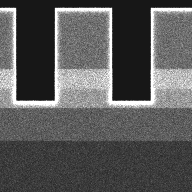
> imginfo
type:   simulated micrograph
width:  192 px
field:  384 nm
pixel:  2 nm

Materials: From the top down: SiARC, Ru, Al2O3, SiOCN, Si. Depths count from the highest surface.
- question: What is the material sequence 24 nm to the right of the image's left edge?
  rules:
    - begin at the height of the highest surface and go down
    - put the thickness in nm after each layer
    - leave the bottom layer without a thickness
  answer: SiARC 122, Ru 40, Al2O3 38, SiOCN 66, Si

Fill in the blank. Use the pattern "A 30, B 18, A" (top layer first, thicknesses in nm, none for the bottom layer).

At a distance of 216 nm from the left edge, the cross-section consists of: SiARC 122, Ru 40, Al2O3 38, SiOCN 66, Si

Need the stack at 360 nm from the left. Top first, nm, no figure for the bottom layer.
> SiARC 122, Ru 40, Al2O3 38, SiOCN 66, Si